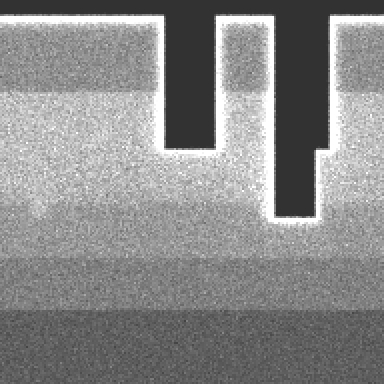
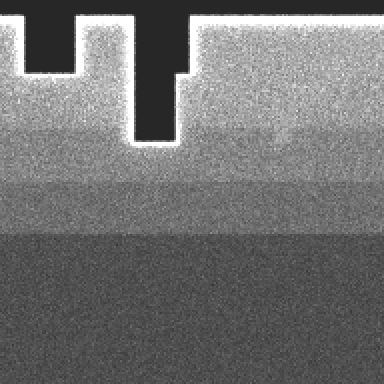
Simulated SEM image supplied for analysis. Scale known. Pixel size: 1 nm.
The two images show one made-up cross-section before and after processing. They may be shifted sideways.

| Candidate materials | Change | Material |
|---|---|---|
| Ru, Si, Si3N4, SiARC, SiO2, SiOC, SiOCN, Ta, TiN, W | removed | SiARC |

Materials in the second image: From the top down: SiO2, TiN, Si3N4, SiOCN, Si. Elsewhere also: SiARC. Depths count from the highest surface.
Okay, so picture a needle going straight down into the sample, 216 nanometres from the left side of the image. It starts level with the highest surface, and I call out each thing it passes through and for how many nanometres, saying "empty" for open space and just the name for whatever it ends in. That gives SiO2 58, TiN 54, Si3N4 54, SiOCN 52, Si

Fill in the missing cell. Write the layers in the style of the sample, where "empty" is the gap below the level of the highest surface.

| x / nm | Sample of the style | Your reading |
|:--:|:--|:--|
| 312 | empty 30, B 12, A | SiO2 58, TiN 54, Si3N4 54, SiOCN 52, Si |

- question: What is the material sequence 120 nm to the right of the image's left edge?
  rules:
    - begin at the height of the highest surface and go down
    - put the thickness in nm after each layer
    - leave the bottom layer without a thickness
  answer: SiO2 126, Si3N4 40, SiOCN 52, Si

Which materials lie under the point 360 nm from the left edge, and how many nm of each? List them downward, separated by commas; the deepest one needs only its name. SiO2 58, TiN 54, Si3N4 54, SiOCN 52, Si